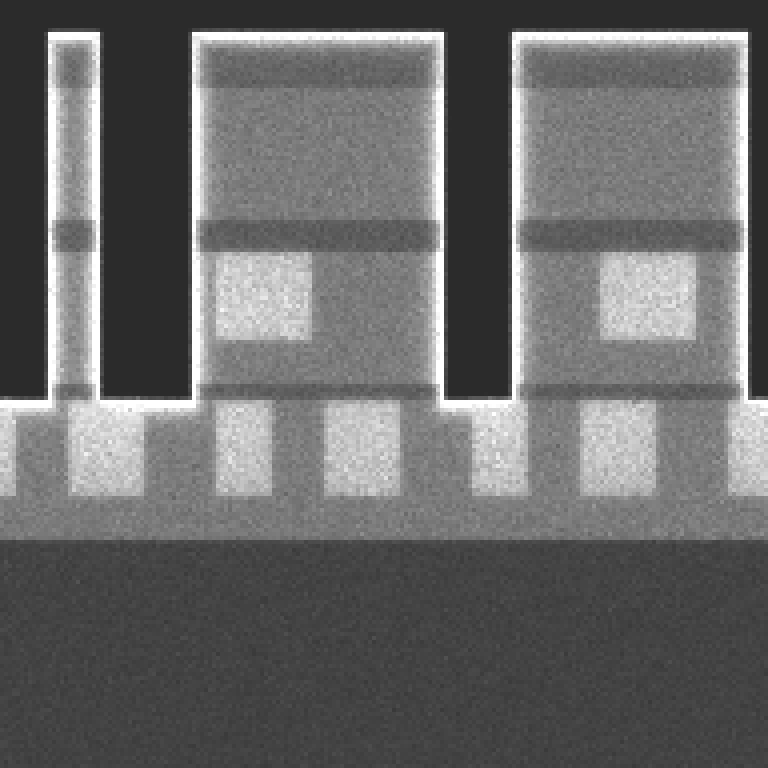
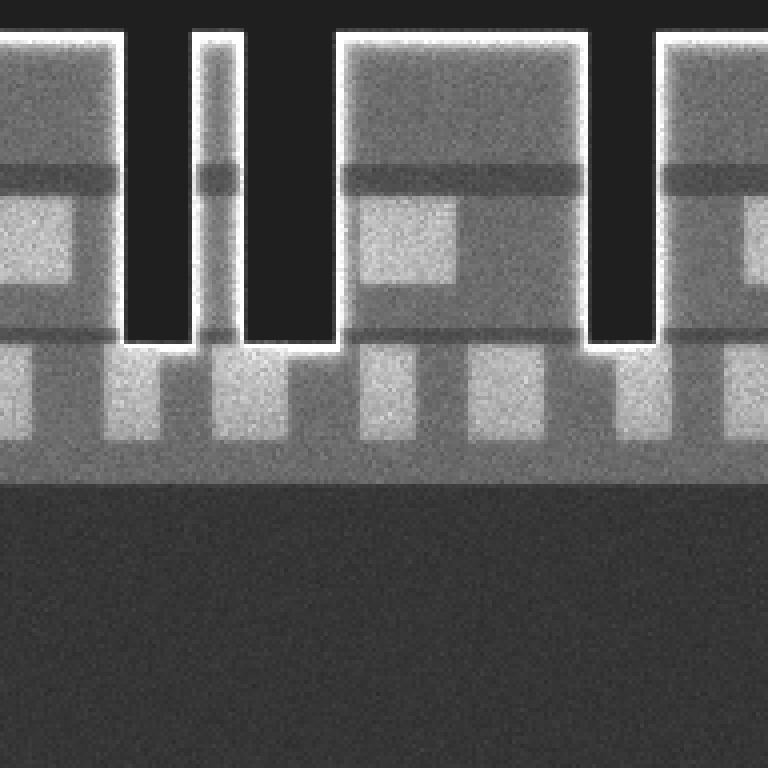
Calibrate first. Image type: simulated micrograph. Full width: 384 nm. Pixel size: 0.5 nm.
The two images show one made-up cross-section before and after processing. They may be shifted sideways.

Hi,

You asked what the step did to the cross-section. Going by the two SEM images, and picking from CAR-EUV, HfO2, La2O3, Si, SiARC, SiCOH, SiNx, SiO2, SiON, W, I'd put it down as SiARC, removed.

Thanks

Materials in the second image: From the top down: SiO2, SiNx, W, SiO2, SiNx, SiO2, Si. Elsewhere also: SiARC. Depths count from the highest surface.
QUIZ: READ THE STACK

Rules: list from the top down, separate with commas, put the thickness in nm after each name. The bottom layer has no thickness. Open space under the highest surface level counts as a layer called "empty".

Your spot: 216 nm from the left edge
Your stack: SiO2 66, SiNx 16, W 44, SiO2 22, SiNx 8, SiO2 70, Si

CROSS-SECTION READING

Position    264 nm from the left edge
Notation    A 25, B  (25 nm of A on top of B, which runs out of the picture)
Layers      SiO2 66, SiNx 16, SiO2 66, SiNx 8, W 48, SiO2 22, Si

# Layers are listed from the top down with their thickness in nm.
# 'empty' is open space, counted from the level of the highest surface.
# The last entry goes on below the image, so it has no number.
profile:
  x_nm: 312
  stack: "empty 156, W 48, SiO2 22, Si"